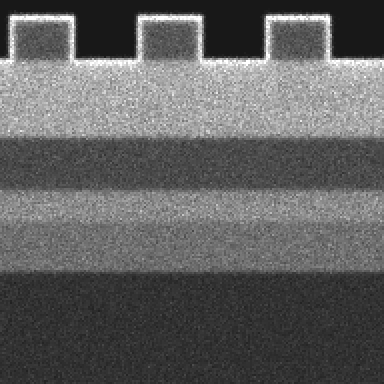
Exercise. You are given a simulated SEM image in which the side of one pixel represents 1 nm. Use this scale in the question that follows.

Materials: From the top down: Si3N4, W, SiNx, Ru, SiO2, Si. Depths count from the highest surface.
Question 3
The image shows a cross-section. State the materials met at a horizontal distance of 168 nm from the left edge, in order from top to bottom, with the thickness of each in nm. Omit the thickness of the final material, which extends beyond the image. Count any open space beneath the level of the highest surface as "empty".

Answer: Si3N4 44, W 78, SiNx 52, Ru 32, SiO2 50, Si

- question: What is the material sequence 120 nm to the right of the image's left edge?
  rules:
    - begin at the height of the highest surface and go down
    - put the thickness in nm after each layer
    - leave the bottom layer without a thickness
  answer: empty 44, W 78, SiNx 52, Ru 32, SiO2 50, Si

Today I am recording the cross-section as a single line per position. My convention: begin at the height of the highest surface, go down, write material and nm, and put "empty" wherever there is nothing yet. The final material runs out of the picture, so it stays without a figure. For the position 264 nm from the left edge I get empty 44, W 78, SiNx 52, Ru 32, SiO2 50, Si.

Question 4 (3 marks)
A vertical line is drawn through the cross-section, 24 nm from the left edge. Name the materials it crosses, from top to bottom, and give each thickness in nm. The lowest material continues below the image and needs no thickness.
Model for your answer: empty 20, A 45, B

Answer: Si3N4 44, W 78, SiNx 52, Ru 32, SiO2 50, Si